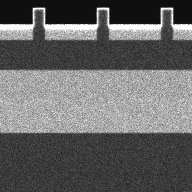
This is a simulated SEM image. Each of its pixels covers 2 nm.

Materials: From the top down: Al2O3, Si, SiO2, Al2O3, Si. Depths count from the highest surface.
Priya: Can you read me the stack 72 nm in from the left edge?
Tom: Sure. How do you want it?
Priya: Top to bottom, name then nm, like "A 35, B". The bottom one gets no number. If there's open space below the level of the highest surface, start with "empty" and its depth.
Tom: Si 124, SiO2 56, Al2O3 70, Si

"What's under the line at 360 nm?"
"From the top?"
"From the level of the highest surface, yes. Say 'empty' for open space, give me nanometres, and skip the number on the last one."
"empty 34, Al2O3 30, Si 60, SiO2 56, Al2O3 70, Si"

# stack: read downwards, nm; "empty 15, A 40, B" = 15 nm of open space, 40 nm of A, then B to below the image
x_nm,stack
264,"empty 34, Al2O3 30, Si 60, SiO2 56, Al2O3 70, Si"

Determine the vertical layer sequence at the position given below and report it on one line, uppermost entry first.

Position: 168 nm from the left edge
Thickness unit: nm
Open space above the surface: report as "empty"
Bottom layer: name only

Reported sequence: empty 34, Al2O3 30, Si 60, SiO2 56, Al2O3 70, Si